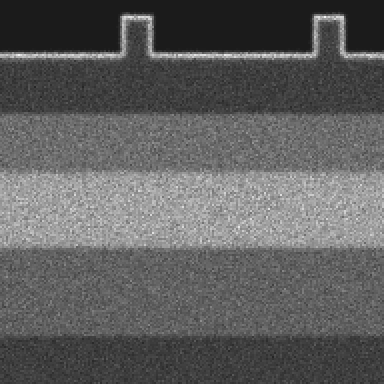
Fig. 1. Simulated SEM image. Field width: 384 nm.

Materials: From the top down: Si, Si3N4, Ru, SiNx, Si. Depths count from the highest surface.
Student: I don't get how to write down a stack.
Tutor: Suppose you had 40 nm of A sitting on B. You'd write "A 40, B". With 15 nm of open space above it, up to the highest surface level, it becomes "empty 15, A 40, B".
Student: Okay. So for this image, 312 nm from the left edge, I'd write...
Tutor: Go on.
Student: empty 38, Si 60, Si3N4 58, Ru 76, SiNx 88, Si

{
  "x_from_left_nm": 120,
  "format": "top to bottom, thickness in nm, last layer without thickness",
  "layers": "empty 38, Si 60, Si3N4 58, Ru 76, SiNx 88, Si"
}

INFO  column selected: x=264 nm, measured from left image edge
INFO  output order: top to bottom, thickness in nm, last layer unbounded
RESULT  empty 38, Si 60, Si3N4 58, Ru 76, SiNx 88, Si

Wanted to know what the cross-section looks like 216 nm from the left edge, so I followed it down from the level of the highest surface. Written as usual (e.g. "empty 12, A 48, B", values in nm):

empty 38, Si 60, Si3N4 58, Ru 76, SiNx 88, Si